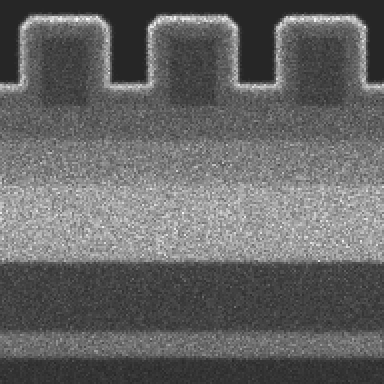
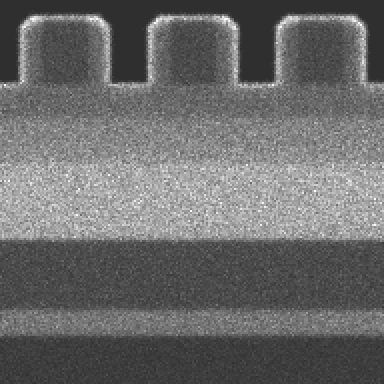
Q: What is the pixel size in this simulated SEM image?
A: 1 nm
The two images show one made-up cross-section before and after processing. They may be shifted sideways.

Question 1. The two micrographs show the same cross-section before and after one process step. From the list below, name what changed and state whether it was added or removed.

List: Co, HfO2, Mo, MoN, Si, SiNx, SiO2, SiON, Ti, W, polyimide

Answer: SiO2, removed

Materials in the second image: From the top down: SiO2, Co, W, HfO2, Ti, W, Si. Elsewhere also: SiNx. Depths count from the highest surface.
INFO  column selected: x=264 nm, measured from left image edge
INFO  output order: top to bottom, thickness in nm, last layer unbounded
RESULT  empty 68, Co 34, W 46, HfO2 76, Ti 70, W 26, Si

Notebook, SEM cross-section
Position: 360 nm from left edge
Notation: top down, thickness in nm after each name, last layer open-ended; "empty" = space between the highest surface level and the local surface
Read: empty 6, SiO2 62, Co 34, W 46, HfO2 76, Ti 70, W 26, Si